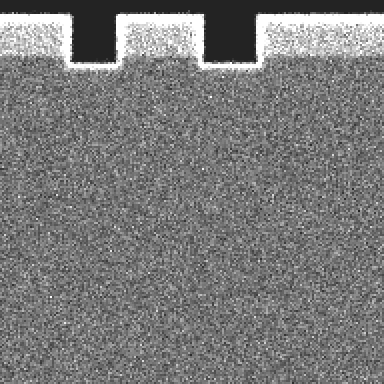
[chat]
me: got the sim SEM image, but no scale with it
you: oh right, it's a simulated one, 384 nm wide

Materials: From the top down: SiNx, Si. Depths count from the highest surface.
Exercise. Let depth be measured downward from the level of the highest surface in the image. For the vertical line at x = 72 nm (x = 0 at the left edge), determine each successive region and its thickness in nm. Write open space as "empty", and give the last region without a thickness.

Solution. empty 48, Si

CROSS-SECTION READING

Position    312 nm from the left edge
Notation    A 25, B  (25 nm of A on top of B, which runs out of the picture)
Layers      SiNx 40, Si